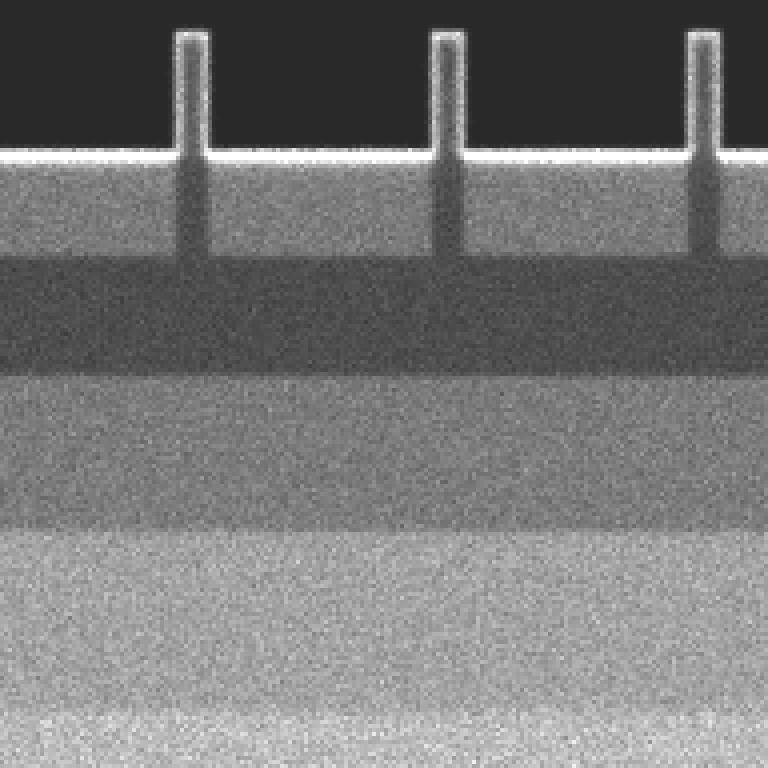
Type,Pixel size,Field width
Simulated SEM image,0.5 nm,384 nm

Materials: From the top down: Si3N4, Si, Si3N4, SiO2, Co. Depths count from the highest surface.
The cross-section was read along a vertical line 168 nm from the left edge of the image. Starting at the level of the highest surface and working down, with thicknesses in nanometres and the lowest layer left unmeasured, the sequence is empty 60, Si3N4 52, Si 60, Si3N4 78, SiO2 90, Co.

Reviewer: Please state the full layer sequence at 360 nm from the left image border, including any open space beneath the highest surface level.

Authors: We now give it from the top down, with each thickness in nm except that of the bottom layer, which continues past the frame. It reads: empty 60, Si3N4 52, Si 60, Si3N4 78, SiO2 90, Co